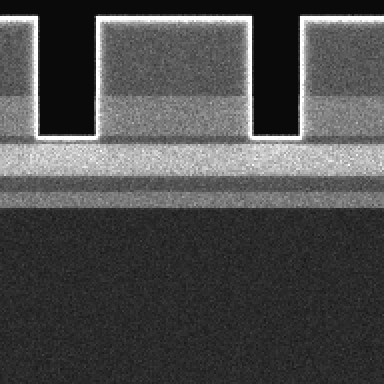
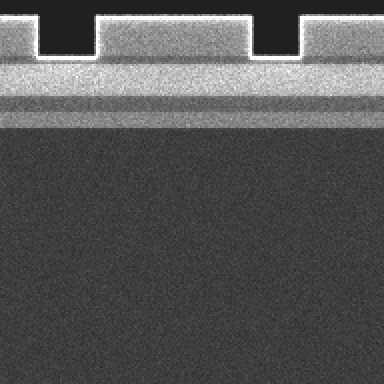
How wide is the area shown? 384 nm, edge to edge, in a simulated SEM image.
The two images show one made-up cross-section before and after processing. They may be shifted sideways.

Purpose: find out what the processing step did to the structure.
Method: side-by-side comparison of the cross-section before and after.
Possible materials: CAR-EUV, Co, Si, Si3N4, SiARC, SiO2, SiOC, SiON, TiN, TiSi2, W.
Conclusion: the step removed SiARC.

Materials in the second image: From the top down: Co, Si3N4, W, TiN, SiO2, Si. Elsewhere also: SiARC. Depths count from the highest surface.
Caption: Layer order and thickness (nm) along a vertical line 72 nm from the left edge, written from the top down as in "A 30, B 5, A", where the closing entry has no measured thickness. empty 40, Si3N4 8, W 32, TiN 16, SiO2 16, Si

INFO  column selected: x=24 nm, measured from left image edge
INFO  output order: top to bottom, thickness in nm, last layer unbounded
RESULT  Co 40, Si3N4 8, W 32, TiN 16, SiO2 16, Si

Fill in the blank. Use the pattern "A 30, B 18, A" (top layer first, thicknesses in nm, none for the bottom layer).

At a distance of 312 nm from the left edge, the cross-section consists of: Co 40, Si3N4 8, W 32, TiN 16, SiO2 16, Si